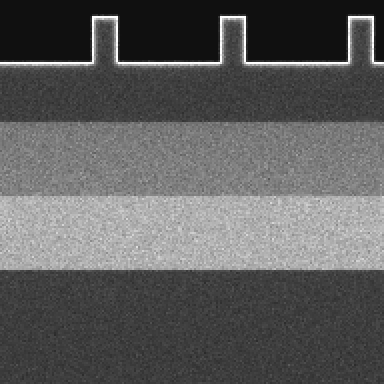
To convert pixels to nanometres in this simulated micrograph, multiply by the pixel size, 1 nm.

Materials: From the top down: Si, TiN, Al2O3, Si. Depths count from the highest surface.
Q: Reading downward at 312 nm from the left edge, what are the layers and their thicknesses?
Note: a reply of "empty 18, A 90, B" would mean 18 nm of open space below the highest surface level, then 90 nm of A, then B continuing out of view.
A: empty 46, Si 60, TiN 74, Al2O3 74, Si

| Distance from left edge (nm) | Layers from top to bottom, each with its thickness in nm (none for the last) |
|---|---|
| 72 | empty 46, Si 60, TiN 74, Al2O3 74, Si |